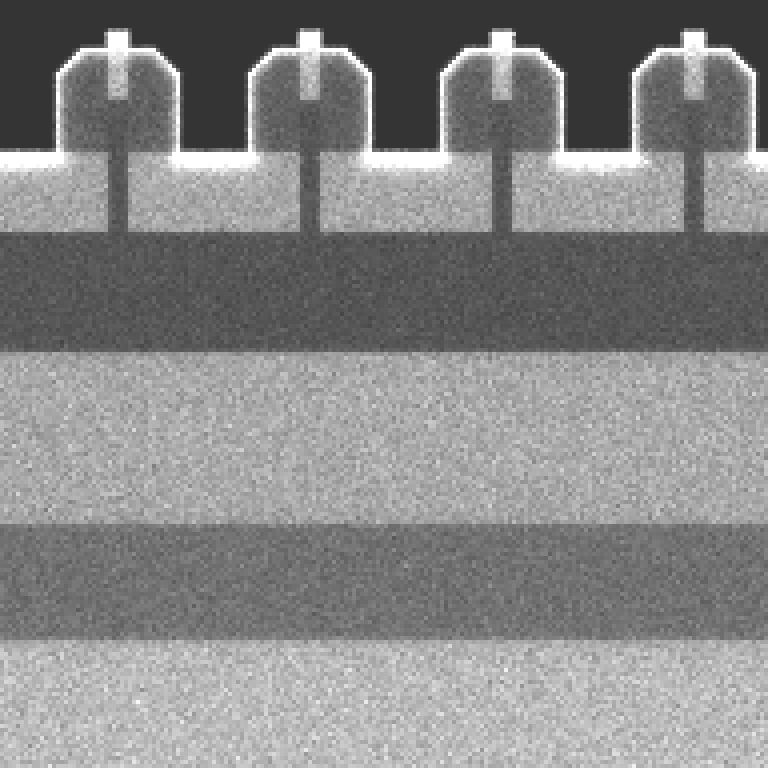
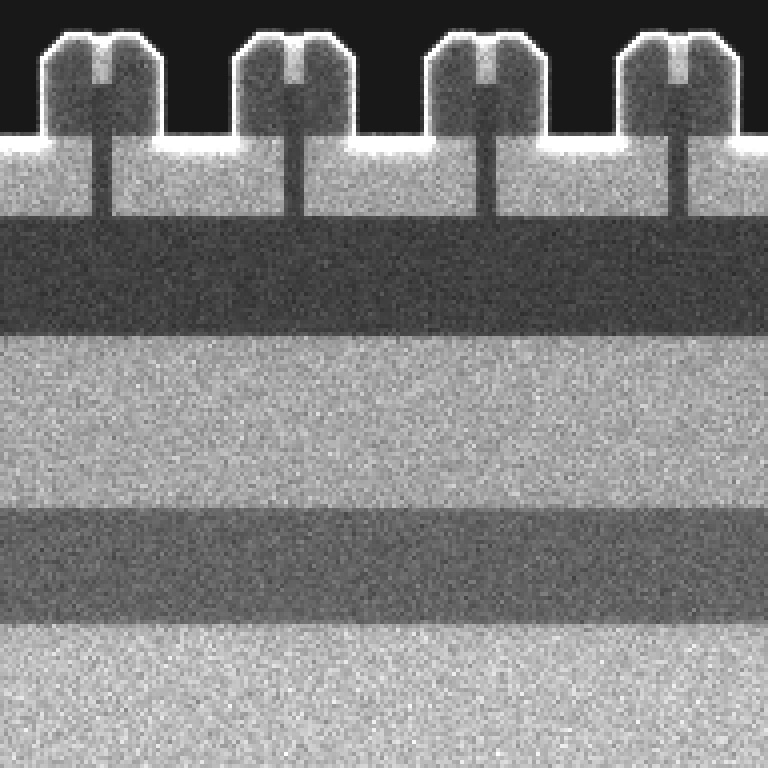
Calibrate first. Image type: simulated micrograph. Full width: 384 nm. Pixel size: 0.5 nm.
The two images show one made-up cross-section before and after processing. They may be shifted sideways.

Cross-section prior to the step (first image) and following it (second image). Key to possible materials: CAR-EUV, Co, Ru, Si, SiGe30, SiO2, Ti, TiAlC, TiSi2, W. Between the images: Ru was removed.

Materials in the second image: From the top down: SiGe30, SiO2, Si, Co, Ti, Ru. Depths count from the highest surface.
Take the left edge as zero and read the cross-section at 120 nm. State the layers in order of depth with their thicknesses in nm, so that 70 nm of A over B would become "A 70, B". empty 8, SiGe30 44, SiO2 40, Si 60, Co 86, Ti 58, Ru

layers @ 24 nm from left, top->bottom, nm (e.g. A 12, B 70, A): empty 8, SiGe30 44, SiO2 40, Si 60, Co 86, Ti 58, Ru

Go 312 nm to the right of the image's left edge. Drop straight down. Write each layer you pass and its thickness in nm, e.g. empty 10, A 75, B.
empty 8, SiGe30 44, SiO2 40, Si 60, Co 86, Ti 58, Ru